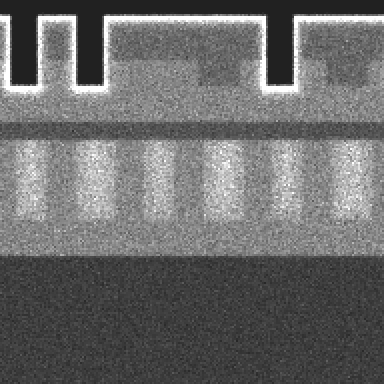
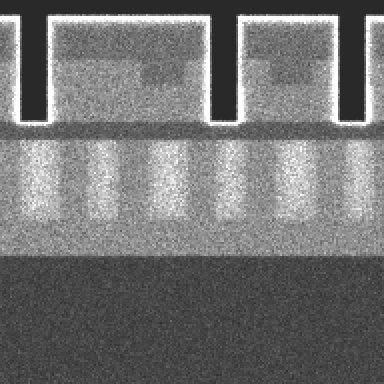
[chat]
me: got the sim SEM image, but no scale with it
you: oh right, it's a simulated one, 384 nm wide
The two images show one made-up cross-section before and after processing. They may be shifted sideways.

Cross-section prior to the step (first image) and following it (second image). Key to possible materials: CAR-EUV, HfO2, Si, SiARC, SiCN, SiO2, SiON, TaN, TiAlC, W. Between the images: SiO2 was removed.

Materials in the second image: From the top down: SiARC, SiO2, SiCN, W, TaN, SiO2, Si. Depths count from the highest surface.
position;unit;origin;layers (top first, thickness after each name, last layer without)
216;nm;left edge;empty 106, SiCN 18, TaN 80, SiO2 36, Si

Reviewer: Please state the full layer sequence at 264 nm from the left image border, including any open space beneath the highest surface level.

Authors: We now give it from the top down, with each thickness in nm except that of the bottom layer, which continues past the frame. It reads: SiARC 44, SiO2 62, SiCN 18, SiO2 116, Si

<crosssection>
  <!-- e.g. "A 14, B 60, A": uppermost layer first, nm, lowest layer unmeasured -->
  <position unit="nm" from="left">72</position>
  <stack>SiARC 44, SiO2 62, SiCN 18, SiO2 116, Si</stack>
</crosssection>